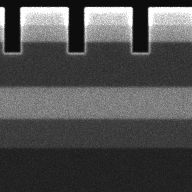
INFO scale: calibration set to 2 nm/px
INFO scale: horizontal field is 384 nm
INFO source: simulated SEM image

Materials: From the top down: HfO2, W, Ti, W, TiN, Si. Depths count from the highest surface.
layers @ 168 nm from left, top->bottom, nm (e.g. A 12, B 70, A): empty 90, Ti 68, W 64, TiN 58, Si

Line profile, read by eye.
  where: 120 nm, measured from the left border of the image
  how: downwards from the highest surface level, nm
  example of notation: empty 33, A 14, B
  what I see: HfO2 34, W 34, Ti 90, W 64, TiN 58, Si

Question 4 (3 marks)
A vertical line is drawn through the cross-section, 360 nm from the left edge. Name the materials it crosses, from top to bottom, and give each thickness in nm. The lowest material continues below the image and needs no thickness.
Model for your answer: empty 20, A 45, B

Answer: HfO2 34, W 34, Ti 90, W 64, TiN 58, Si